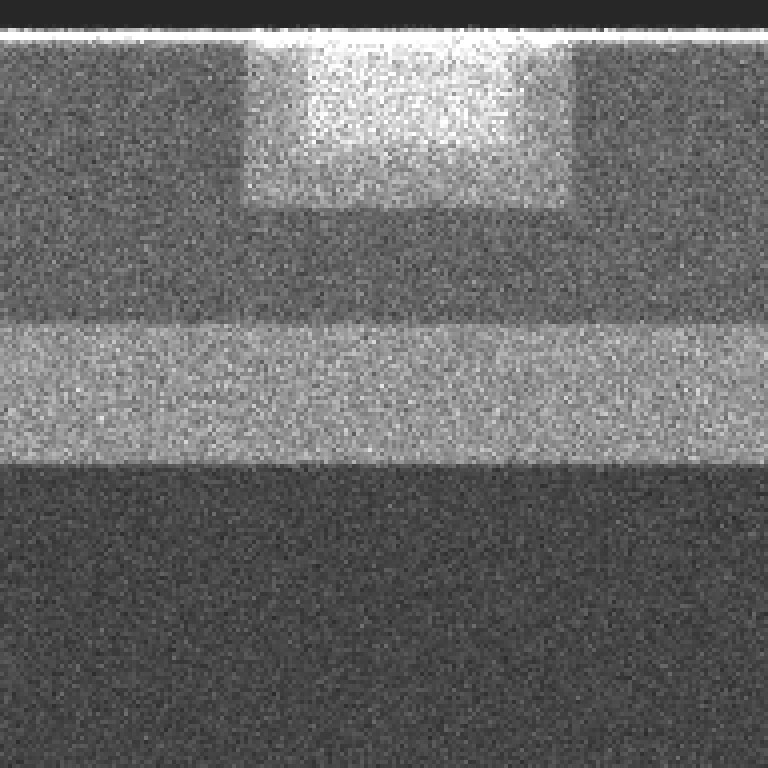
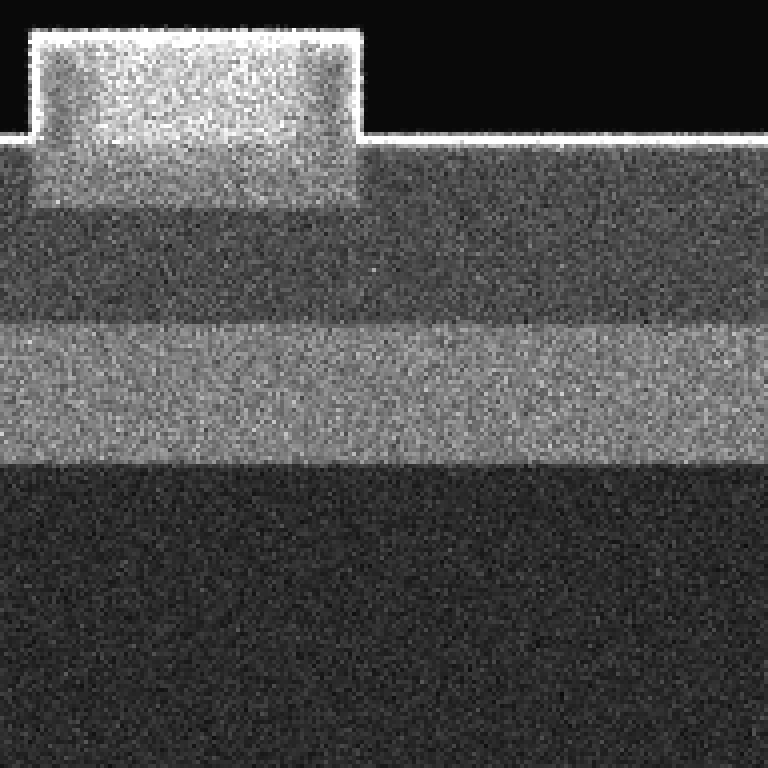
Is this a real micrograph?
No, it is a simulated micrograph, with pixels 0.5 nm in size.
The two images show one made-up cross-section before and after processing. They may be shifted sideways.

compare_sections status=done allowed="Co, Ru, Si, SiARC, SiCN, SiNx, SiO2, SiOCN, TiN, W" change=removed material="SiNx"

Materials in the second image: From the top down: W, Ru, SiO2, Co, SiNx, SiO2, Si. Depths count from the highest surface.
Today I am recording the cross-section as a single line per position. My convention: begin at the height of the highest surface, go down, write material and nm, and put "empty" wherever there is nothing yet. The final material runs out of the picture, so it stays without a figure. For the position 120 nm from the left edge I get W 56, Ru 12, SiO2 10, Co 10, SiNx 58, SiO2 70, Si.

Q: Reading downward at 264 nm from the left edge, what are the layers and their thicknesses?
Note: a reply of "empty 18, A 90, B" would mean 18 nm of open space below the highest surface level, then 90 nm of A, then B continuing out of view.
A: empty 52, SiNx 94, SiO2 70, Si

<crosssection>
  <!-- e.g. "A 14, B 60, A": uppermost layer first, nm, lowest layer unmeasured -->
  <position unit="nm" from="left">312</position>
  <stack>empty 52, SiNx 94, SiO2 70, Si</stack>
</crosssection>